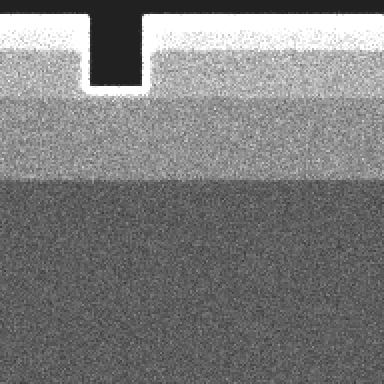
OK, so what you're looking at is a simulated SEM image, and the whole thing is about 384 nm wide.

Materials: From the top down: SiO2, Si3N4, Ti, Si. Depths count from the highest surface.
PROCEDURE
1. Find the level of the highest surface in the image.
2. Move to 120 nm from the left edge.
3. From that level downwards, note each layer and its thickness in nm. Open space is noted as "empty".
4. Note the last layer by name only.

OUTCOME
empty 72, Si3N4 10, Ti 82, Si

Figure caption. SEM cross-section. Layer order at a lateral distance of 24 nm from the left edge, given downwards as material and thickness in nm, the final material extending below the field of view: SiO2 34, Si3N4 48, Ti 82, Si